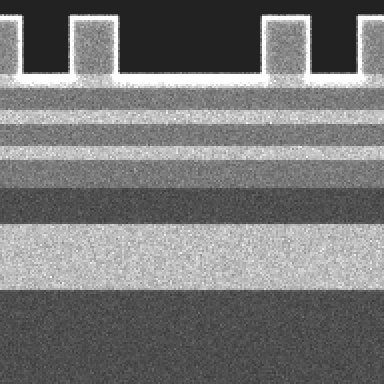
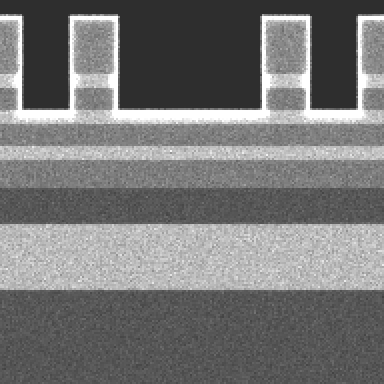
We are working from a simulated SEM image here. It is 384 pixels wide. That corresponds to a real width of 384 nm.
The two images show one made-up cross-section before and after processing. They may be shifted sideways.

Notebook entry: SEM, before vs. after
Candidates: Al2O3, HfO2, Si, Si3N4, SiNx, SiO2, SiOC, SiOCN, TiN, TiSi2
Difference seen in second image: Al2O3 and SiNx removed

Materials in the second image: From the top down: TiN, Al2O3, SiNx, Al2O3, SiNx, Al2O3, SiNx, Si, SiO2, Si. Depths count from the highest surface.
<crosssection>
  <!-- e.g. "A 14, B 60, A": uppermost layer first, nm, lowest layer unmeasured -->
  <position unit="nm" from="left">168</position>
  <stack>empty 94, Al2O3 14, SiNx 22, Al2O3 14, SiNx 28, Si 36, SiO2 66, Si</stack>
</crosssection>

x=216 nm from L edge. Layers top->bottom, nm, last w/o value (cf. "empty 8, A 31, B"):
empty 94, Al2O3 14, SiNx 22, Al2O3 14, SiNx 28, Si 36, SiO2 66, Si